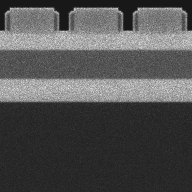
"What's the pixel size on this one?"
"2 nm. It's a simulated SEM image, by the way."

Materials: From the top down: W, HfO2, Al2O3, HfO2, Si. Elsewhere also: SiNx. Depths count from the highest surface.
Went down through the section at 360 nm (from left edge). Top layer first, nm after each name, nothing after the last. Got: W 52, HfO2 32, Al2O3 58, HfO2 46, Si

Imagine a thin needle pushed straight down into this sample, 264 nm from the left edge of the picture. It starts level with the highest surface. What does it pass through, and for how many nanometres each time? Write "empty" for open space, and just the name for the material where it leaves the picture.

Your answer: empty 46, W 6, HfO2 32, Al2O3 58, HfO2 46, Si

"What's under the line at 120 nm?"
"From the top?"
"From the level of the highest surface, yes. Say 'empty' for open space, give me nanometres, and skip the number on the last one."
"empty 46, W 6, HfO2 32, Al2O3 58, HfO2 46, Si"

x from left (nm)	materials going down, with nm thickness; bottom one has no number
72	W 52, HfO2 32, Al2O3 58, HfO2 46, Si